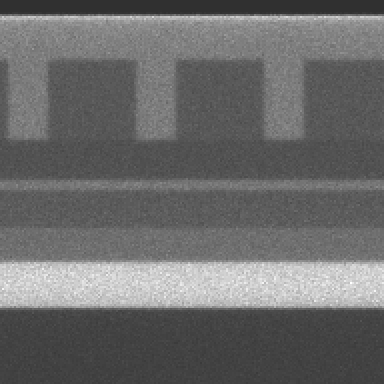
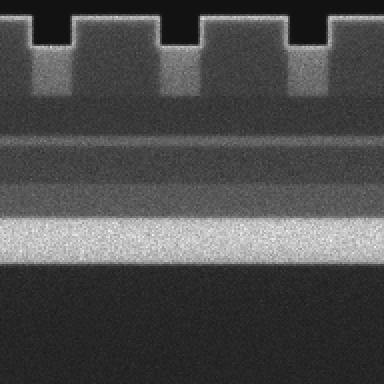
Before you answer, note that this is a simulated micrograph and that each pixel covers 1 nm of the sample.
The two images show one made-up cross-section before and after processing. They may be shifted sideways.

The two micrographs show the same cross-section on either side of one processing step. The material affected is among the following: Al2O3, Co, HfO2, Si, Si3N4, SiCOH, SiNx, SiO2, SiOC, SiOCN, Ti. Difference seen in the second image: Co removed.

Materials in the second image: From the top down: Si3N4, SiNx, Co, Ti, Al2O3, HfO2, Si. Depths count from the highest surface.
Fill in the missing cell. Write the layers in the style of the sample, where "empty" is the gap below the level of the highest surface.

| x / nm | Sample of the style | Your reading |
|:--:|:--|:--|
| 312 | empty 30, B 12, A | empty 30, Co 50, SiNx 40, Co 10, Ti 38, Al2O3 34, HfO2 46, Si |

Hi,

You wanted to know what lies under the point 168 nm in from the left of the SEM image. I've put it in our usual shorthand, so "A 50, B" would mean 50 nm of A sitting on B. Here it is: empty 30, Co 50, SiNx 40, Co 10, Ti 38, Al2O3 34, HfO2 46, Si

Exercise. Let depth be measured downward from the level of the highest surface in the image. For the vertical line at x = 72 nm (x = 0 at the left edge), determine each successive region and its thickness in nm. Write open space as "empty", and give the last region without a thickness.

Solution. Si3N4 80, SiNx 40, Co 10, Ti 38, Al2O3 34, HfO2 46, Si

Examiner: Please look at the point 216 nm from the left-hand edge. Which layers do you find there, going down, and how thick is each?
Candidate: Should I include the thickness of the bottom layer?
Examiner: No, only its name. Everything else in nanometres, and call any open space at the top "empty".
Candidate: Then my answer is Si3N4 80, SiNx 40, Co 10, Ti 38, Al2O3 34, HfO2 46, Si